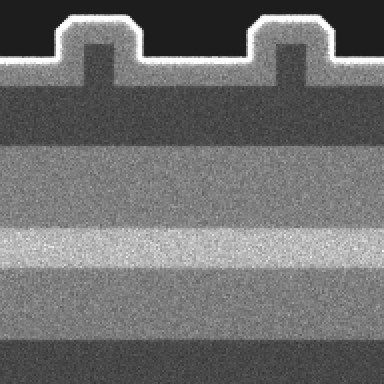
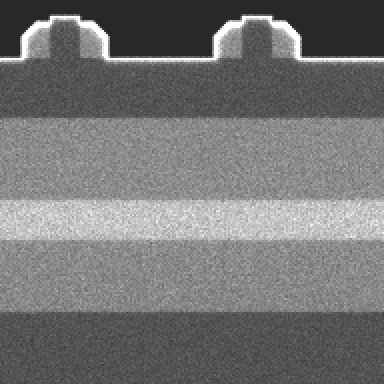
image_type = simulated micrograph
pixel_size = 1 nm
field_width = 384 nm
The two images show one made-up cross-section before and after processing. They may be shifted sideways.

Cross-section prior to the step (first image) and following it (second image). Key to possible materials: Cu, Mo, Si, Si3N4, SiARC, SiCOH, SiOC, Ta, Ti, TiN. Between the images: Si3N4 was removed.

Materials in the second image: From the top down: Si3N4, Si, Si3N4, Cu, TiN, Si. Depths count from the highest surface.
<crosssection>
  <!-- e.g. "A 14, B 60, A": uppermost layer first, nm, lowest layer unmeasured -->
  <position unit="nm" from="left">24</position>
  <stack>empty 18, Si3N4 24, Si 60, Si3N4 82, Cu 40, TiN 72, Si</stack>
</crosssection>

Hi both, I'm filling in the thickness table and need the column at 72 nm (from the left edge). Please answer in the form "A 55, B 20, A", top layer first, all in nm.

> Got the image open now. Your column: Si 102, Si3N4 82, Cu 40, TiN 72, Si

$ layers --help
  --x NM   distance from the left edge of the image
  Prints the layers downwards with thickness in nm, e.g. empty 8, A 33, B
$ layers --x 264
Si 102, Si3N4 82, Cu 40, TiN 72, Si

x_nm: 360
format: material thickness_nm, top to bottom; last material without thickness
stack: empty 42, Si 60, Si3N4 82, Cu 40, TiN 72, Si